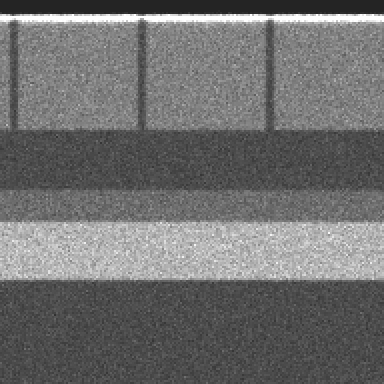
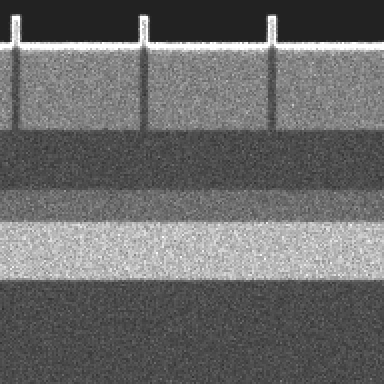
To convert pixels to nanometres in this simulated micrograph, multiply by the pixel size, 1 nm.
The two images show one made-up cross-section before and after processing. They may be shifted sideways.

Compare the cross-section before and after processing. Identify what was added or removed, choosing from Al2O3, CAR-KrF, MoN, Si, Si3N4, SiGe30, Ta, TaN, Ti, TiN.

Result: Si3N4 removed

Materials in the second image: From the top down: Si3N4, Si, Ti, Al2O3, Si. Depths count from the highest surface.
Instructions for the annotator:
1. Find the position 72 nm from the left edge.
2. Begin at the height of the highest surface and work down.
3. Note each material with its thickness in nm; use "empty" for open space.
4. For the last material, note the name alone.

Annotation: empty 28, Si3N4 86, Si 60, Ti 32, Al2O3 58, Si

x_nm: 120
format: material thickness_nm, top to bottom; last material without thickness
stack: empty 28, Si3N4 86, Si 60, Ti 32, Al2O3 58, Si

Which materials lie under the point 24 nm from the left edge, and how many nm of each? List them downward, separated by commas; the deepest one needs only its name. empty 28, Si3N4 86, Si 60, Ti 32, Al2O3 58, Si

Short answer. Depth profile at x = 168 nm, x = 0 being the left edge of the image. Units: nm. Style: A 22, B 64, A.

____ empty 28, Si3N4 86, Si 60, Ti 32, Al2O3 58, Si